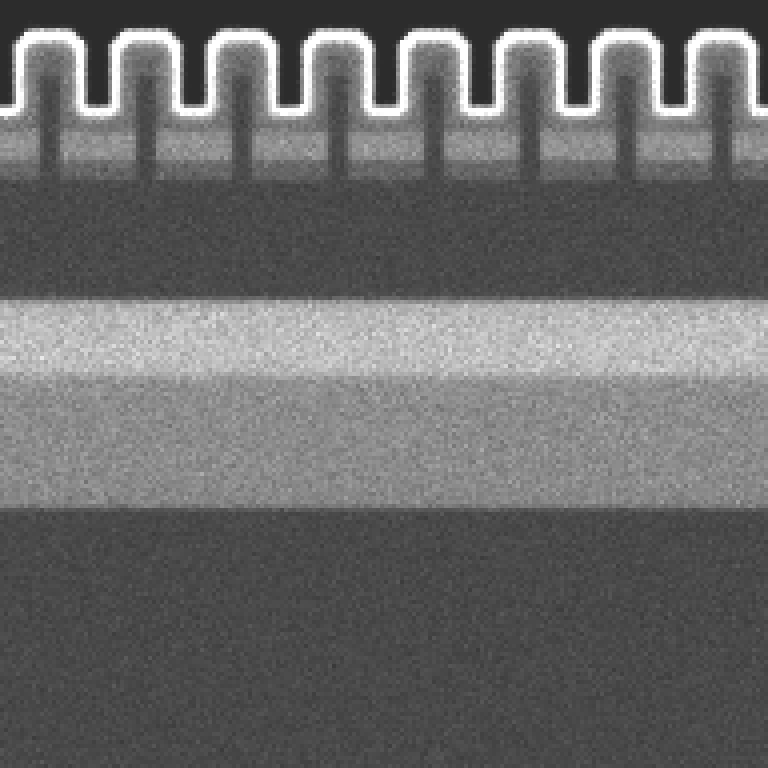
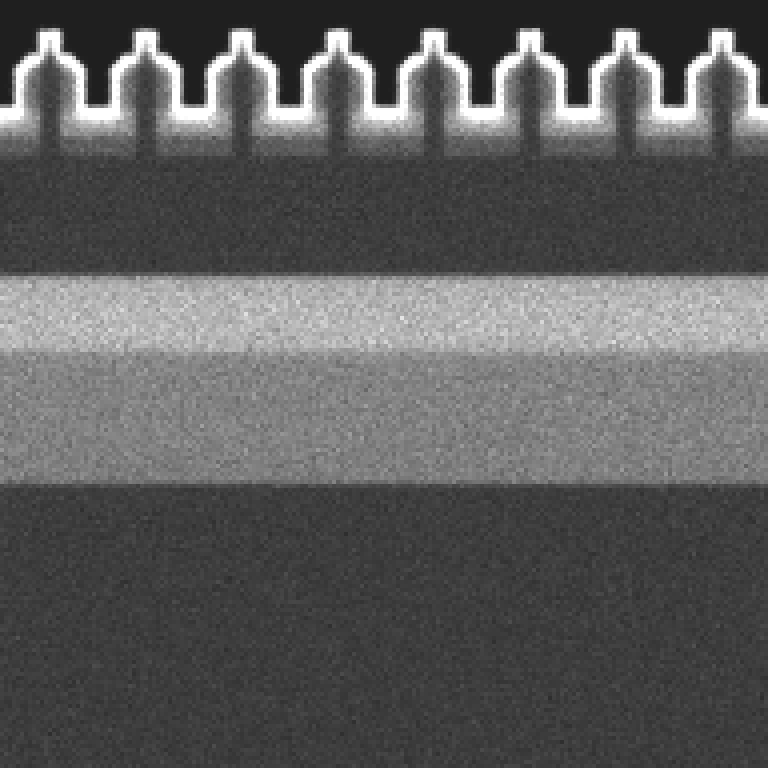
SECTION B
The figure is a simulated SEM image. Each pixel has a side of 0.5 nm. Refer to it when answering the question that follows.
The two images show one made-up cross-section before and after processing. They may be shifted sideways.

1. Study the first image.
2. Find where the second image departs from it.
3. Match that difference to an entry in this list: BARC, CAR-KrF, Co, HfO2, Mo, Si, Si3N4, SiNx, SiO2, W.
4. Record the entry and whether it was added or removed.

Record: Si3N4 / removed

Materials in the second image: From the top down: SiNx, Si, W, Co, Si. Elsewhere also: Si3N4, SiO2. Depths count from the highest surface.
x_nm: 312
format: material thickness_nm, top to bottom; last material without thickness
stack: SiNx 10, Si 112, W 38, Co 66, Si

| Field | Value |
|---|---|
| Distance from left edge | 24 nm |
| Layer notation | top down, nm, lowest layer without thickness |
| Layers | SiNx 10, Si 112, W 38, Co 66, Si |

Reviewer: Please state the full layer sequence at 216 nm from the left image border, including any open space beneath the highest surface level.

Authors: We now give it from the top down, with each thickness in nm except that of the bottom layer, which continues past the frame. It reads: SiNx 10, Si 112, W 38, Co 66, Si